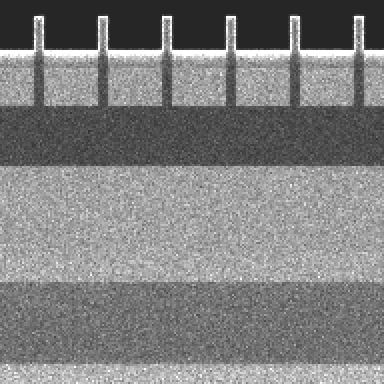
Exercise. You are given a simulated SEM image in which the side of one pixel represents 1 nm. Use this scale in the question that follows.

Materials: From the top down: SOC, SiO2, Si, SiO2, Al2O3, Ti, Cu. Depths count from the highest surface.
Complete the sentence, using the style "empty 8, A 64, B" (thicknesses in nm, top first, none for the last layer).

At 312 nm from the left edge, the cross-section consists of empty 34, SOC 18, SiO2 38, Si 60, SiO2 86, Al2O3 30, Ti 82, Cu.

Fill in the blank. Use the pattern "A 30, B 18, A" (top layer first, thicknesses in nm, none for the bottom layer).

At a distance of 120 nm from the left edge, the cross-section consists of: empty 34, SOC 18, SiO2 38, Si 60, SiO2 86, Al2O3 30, Ti 82, Cu